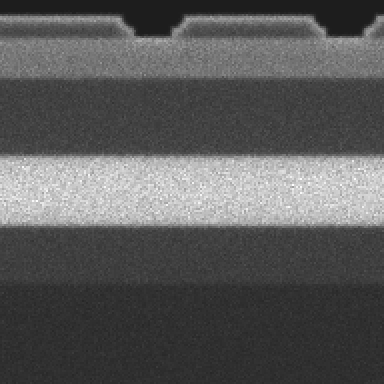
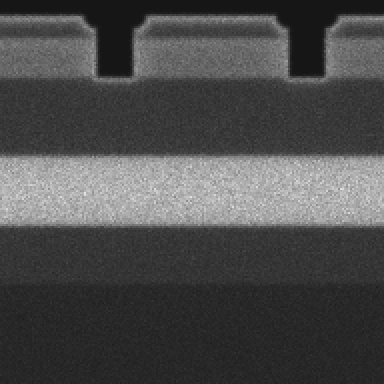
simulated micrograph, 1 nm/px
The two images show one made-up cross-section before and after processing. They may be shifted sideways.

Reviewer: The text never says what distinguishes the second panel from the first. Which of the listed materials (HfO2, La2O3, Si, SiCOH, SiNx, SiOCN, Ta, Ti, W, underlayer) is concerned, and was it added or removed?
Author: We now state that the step removed W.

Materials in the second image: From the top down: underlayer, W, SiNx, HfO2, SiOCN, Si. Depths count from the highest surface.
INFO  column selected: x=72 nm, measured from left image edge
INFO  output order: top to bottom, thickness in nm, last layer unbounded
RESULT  underlayer 22, W 40, SiNx 78, HfO2 70, SiOCN 58, Si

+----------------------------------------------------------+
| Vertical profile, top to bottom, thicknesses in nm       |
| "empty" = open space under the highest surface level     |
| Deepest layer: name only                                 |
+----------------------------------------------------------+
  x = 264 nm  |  underlayer 22, W 40, SiNx 78, HfO2 70, SiOCN 58, Si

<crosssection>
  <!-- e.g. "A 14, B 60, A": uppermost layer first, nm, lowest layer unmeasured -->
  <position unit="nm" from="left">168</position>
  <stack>underlayer 22, W 40, SiNx 78, HfO2 70, SiOCN 58, Si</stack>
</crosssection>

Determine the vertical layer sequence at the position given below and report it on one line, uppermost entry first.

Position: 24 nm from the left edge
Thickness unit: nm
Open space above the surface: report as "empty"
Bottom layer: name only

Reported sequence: underlayer 22, W 40, SiNx 78, HfO2 70, SiOCN 58, Si